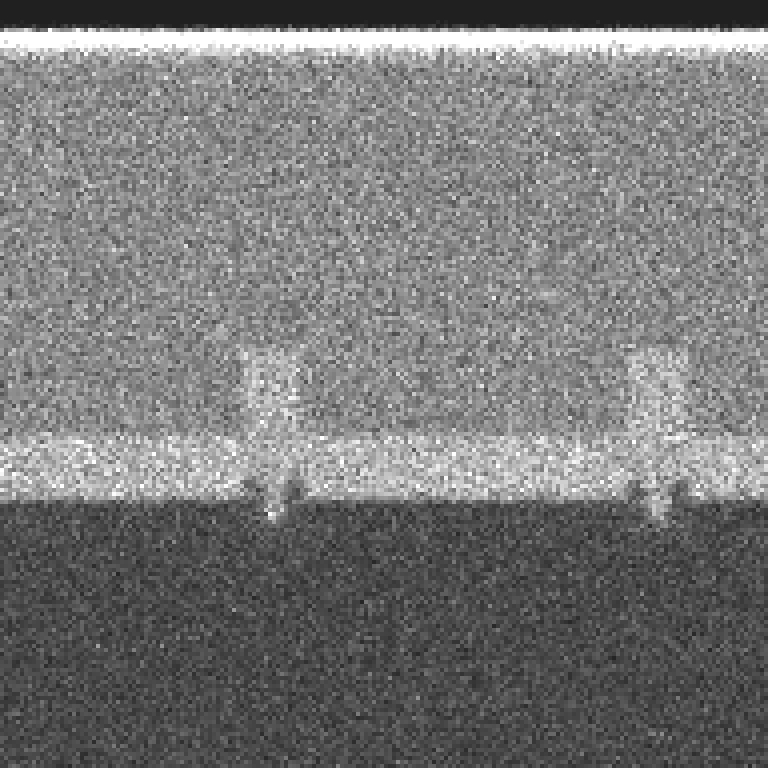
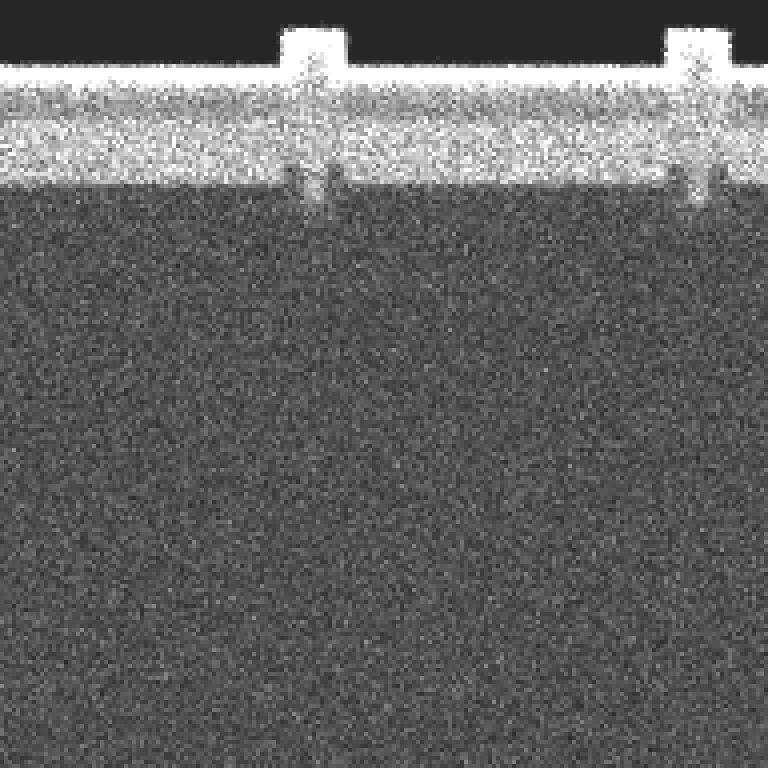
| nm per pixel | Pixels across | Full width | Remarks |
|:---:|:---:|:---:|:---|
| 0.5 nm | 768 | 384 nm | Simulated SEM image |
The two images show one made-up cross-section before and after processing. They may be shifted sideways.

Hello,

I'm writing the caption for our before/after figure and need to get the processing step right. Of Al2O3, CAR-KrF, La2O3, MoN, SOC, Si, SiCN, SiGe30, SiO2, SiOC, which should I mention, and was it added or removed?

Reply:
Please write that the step removed SOC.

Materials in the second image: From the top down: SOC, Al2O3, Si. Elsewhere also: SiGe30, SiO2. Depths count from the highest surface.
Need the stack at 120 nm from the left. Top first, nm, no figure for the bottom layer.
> empty 18, SOC 26, Al2O3 32, Si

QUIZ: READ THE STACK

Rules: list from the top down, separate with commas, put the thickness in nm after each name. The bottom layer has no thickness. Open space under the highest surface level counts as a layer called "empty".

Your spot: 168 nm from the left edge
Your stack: SiO2 66, SiGe30 30, Si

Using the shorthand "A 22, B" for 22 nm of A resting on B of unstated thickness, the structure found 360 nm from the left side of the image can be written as SiO2 66, SiGe30 30, Si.